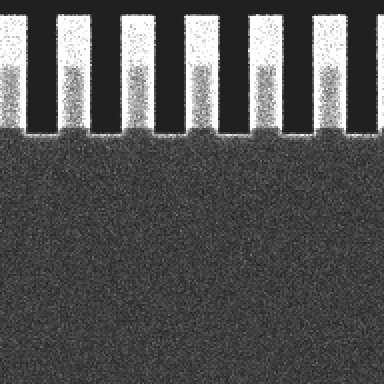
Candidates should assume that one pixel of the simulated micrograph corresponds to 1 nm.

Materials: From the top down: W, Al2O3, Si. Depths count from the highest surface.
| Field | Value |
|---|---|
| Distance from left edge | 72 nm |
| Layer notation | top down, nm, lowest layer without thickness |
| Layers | W 50, Al2O3 62, Si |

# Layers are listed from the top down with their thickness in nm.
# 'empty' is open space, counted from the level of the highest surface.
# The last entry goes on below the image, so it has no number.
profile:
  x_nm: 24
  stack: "W 50, Al2O3 62, Si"